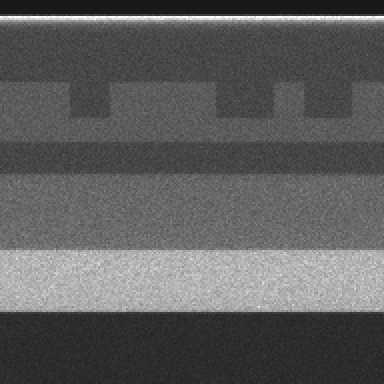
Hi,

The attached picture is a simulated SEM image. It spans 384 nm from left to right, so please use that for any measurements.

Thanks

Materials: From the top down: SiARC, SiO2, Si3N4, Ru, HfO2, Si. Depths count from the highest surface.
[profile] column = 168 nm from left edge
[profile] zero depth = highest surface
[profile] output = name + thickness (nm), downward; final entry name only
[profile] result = SiARC 66, SiO2 60, Si3N4 32, Ru 76, HfO2 62, Si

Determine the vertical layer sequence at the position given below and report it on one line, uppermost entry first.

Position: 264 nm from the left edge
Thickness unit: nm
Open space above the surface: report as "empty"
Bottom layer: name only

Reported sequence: SiARC 102, SiO2 24, Si3N4 32, Ru 76, HfO2 62, Si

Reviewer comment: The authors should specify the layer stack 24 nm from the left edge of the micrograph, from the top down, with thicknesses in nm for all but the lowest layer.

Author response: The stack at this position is SiARC 66, SiO2 60, Si3N4 32, Ru 76, HfO2 62, Si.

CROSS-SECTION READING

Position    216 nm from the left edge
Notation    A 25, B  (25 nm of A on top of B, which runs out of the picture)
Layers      SiARC 102, SiO2 24, Si3N4 32, Ru 76, HfO2 62, Si